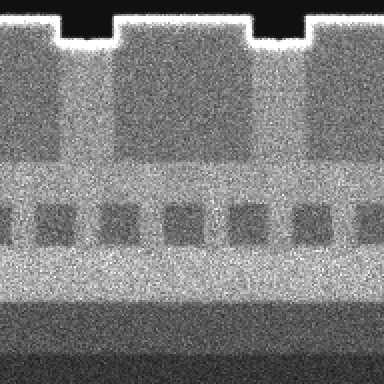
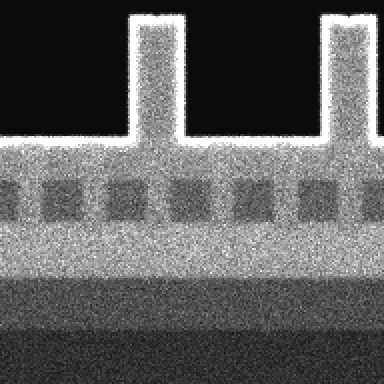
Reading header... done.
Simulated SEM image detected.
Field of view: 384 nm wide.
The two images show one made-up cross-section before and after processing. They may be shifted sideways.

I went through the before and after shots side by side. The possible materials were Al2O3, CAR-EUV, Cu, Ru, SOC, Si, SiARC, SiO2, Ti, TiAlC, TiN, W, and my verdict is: removed, SOC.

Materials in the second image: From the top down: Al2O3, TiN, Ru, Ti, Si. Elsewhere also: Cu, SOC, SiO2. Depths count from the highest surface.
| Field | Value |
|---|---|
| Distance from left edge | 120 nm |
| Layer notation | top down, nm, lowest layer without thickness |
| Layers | empty 122, Al2O3 42, TiN 42, Ru 56, Ti 52, Si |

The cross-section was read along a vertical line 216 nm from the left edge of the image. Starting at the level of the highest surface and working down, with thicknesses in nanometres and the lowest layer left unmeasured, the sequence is empty 122, Cu 92, Ru 48, Ti 52, Si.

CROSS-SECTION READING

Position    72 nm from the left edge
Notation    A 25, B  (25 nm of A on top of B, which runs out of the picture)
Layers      empty 122, Al2O3 42, TiN 42, Ru 56, Ti 52, Si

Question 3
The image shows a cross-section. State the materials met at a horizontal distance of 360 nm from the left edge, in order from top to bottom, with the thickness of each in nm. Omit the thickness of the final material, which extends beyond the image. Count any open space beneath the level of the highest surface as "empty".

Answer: SiO2 122, Cu 92, Ru 48, Ti 52, Si